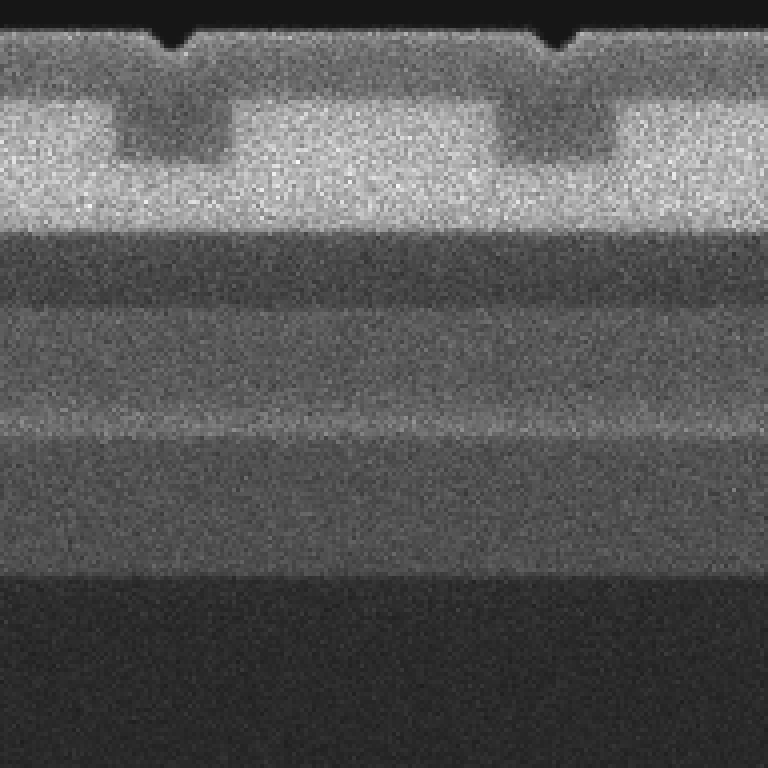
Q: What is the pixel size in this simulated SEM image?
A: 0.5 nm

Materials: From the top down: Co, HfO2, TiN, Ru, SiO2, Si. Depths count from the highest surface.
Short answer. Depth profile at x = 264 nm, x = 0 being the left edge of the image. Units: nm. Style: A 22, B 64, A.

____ Co 66, HfO2 34, TiN 38, Ru 64, SiO2 70, Si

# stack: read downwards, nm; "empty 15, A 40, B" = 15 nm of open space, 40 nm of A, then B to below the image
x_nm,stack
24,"Co 34, HfO2 66, TiN 38, Ru 64, SiO2 70, Si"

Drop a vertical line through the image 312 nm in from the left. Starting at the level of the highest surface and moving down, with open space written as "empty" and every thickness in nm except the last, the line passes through Co 34, HfO2 66, TiN 38, Ru 64, SiO2 70, Si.